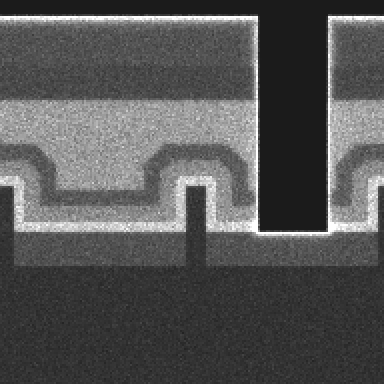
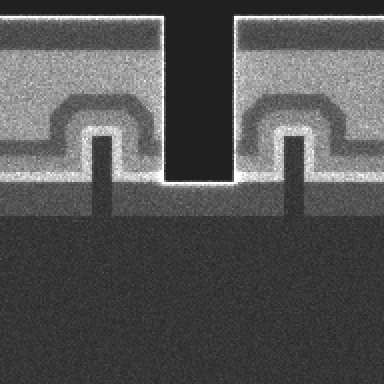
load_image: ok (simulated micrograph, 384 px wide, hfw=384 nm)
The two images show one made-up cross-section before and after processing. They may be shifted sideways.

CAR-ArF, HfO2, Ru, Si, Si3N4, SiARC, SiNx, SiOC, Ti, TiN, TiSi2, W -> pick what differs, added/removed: SiARC removed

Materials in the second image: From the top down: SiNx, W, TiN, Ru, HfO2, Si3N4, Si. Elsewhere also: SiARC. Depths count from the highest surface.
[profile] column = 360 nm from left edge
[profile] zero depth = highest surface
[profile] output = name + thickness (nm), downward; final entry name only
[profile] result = SiNx 34, W 90, TiN 16, Ru 16, HfO2 10, Si3N4 34, Si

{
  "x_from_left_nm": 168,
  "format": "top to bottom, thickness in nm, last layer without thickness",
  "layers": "empty 166, Si3N4 34, Si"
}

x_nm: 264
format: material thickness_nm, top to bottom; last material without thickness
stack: SiNx 34, W 44, TiN 22, Ru 56, HfO2 10, Si3N4 34, Si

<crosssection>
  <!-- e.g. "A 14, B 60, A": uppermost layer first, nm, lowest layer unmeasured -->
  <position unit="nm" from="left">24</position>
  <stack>SiNx 34, W 90, TiN 16, Ru 16, HfO2 10, Si3N4 34, Si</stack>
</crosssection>